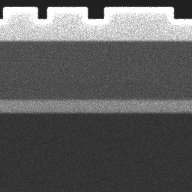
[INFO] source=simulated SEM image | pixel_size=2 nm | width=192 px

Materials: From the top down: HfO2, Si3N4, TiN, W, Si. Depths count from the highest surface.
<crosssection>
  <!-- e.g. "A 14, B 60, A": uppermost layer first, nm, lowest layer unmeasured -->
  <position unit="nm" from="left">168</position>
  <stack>HfO2 66, Si3N4 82, TiN 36, W 26, Si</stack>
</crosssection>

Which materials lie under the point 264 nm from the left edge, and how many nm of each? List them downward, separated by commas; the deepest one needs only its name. HfO2 66, Si3N4 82, TiN 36, W 26, Si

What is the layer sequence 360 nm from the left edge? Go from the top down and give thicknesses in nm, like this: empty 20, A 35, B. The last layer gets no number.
empty 24, HfO2 42, Si3N4 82, TiN 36, W 26, Si